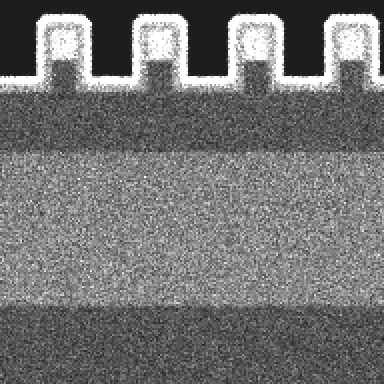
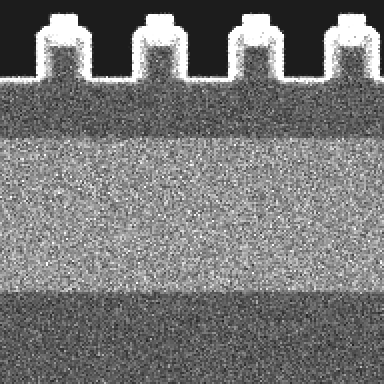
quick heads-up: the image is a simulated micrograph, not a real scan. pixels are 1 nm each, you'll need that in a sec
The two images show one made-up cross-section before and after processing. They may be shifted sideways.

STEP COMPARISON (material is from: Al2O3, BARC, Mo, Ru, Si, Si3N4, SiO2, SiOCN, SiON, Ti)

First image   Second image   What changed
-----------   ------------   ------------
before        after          Si3N4, removed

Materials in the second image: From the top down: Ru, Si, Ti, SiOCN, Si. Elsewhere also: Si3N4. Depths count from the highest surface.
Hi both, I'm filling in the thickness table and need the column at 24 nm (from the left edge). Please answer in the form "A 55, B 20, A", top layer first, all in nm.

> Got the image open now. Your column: empty 62, Si 60, Ti 64, SiOCN 90, Si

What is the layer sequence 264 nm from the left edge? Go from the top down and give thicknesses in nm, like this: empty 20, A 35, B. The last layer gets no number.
Ru 30, Si 92, Ti 64, SiOCN 90, Si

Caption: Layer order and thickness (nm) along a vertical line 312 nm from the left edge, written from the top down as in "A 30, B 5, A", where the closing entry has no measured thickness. empty 62, Si 60, Ti 64, SiOCN 90, Si